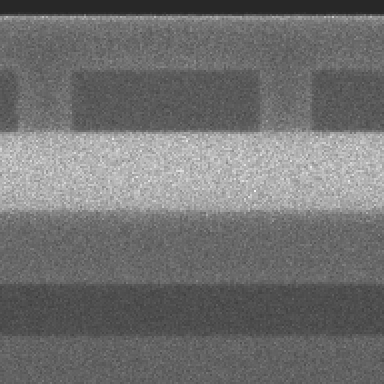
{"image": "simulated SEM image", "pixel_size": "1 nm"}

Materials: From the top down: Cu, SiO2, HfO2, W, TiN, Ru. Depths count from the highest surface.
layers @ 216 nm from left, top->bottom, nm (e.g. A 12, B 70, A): Cu 54, SiO2 62, HfO2 78, W 74, TiN 52, Ru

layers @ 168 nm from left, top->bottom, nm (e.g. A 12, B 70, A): Cu 54, SiO2 62, HfO2 78, W 74, TiN 52, Ru